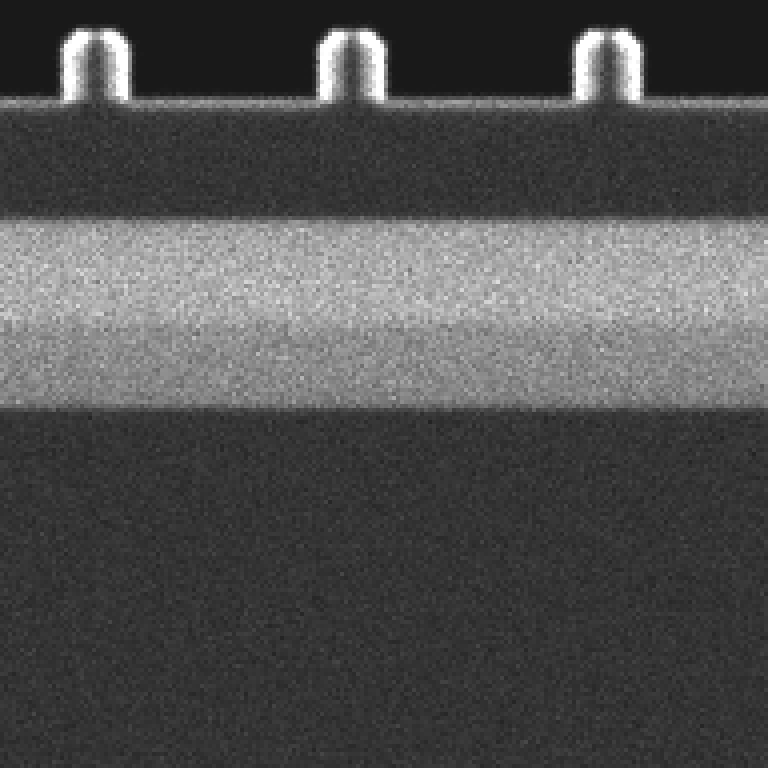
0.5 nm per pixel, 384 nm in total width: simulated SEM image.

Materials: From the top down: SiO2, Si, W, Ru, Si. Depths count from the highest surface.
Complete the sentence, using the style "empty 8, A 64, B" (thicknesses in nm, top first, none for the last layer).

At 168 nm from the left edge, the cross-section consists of SiO2 34, Si 60, W 52, Ru 42, Si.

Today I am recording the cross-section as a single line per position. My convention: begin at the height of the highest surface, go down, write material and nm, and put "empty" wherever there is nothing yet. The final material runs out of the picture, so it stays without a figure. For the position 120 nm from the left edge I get empty 34, Si 60, W 52, Ru 42, Si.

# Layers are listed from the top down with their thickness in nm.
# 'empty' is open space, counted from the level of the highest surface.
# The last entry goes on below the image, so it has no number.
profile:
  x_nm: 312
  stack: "SiO2 34, Si 60, W 52, Ru 42, Si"